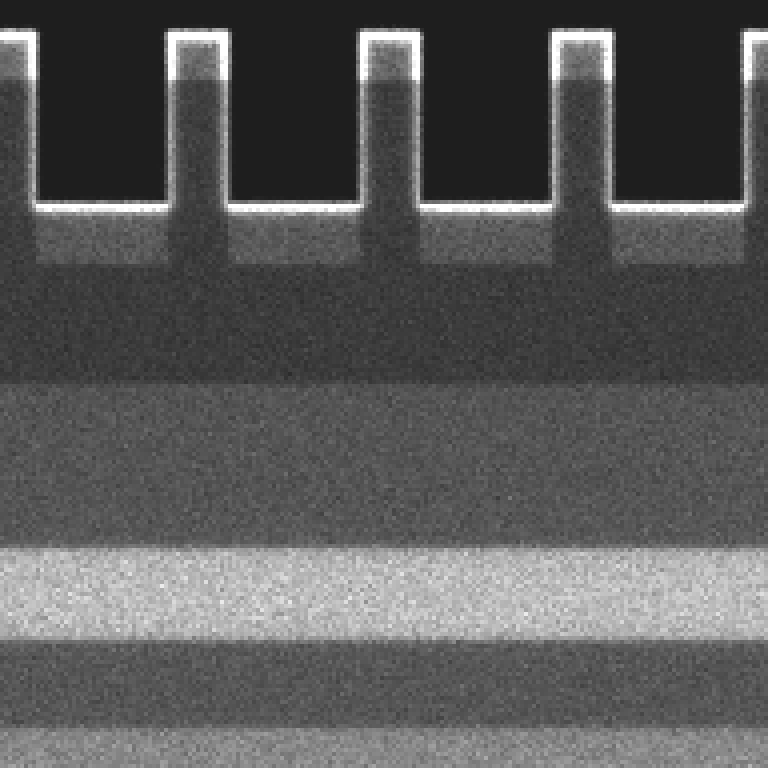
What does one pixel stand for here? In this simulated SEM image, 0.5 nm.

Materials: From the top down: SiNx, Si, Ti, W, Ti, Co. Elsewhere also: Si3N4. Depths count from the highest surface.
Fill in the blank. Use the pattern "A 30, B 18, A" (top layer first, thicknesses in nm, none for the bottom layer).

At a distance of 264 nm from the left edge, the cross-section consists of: empty 86, SiNx 30, Si 60, Ti 82, W 46, Ti 44, Co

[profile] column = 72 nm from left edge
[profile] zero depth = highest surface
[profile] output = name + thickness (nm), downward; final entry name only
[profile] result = empty 86, SiNx 30, Si 60, Ti 82, W 46, Ti 44, Co